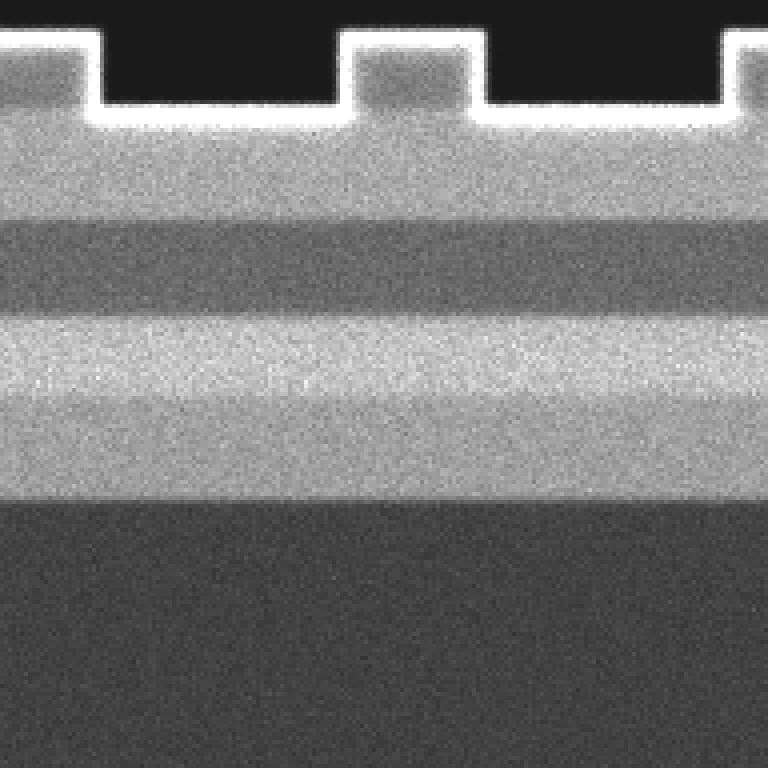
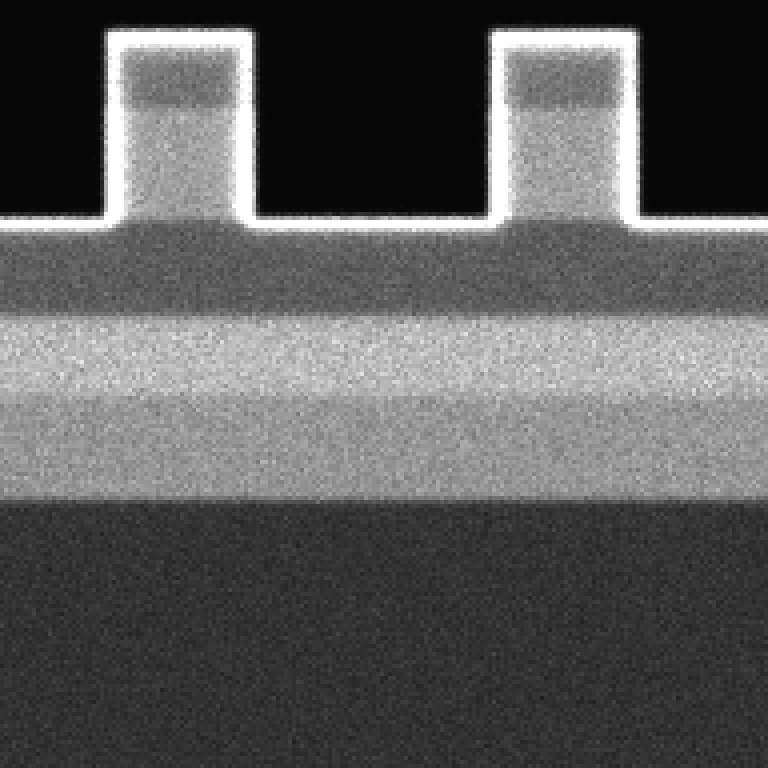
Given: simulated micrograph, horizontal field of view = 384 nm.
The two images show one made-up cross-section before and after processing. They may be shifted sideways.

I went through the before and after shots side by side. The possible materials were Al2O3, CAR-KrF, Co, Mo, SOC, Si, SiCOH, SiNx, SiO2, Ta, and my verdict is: removed, Al2O3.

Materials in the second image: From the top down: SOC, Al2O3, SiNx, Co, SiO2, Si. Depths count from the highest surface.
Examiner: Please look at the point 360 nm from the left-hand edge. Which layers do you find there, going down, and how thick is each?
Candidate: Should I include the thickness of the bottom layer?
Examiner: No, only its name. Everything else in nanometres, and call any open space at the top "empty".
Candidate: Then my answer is empty 94, SiNx 48, Co 40, SiO2 52, Si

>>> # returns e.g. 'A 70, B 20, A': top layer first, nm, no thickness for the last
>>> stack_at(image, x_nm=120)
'SOC 38, Al2O3 56, SiNx 48, Co 40, SiO2 52, Si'